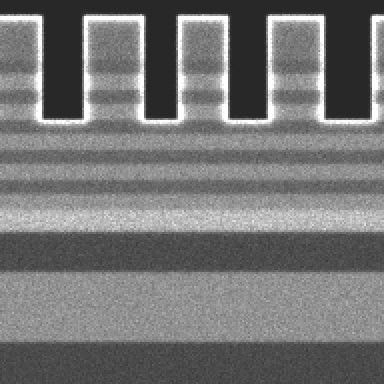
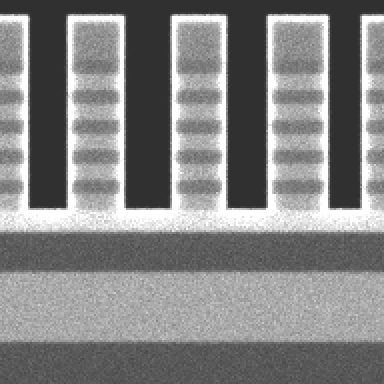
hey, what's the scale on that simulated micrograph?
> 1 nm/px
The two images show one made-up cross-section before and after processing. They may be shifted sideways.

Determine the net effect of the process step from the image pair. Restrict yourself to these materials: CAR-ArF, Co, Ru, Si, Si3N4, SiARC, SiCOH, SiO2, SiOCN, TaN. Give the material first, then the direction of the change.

SiO2 and SiOCN: removed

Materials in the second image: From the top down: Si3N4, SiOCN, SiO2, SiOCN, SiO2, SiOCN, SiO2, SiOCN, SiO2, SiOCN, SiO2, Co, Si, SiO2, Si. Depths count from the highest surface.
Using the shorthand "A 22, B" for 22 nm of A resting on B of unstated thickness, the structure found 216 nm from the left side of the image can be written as Si3N4 44, SiOCN 14, SiO2 16, SiOCN 14, SiO2 16, SiOCN 14, SiO2 16, SiOCN 14, SiO2 16, SiOCN 14, SiO2 16, Co 22, Si 40, SiO2 70, Si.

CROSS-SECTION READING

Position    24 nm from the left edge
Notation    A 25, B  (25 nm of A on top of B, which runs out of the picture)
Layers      Si3N4 44, SiOCN 14, SiO2 16, SiOCN 14, SiO2 16, SiOCN 14, SiO2 16, SiOCN 14, SiO2 16, SiOCN 14, SiO2 16, Co 22, Si 40, SiO2 70, Si